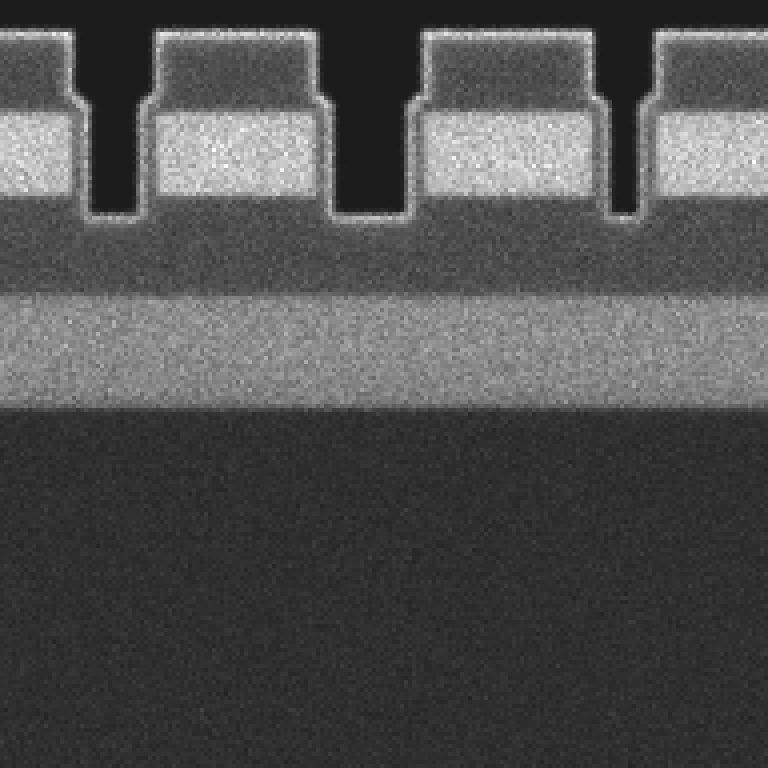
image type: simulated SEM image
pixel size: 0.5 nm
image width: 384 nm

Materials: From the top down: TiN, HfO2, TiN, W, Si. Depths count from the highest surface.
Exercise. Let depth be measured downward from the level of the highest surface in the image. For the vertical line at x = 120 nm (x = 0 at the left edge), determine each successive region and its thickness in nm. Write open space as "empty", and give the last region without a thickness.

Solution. TiN 40, HfO2 42, TiN 50, W 56, Si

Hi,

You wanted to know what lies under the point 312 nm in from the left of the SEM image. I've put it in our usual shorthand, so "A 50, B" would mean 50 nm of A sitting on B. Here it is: empty 92, TiN 40, W 56, Si